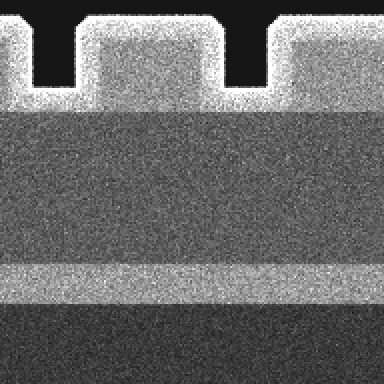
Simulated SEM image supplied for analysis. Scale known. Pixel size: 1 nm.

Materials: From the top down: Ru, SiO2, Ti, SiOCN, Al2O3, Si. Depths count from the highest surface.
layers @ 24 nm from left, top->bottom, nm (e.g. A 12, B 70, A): empty 6, Ru 90, Ti 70, SiOCN 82, Al2O3 40, Si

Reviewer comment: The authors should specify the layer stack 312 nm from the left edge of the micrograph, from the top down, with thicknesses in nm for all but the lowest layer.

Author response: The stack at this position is Ru 24, SiO2 72, Ti 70, SiOCN 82, Al2O3 40, Si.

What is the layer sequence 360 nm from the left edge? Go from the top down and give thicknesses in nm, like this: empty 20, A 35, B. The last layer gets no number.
Ru 24, SiO2 72, Ti 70, SiOCN 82, Al2O3 40, Si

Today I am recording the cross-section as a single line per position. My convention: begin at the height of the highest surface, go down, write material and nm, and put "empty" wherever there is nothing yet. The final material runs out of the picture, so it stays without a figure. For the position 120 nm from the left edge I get Ru 24, SiO2 72, Ti 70, SiOCN 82, Al2O3 40, Si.